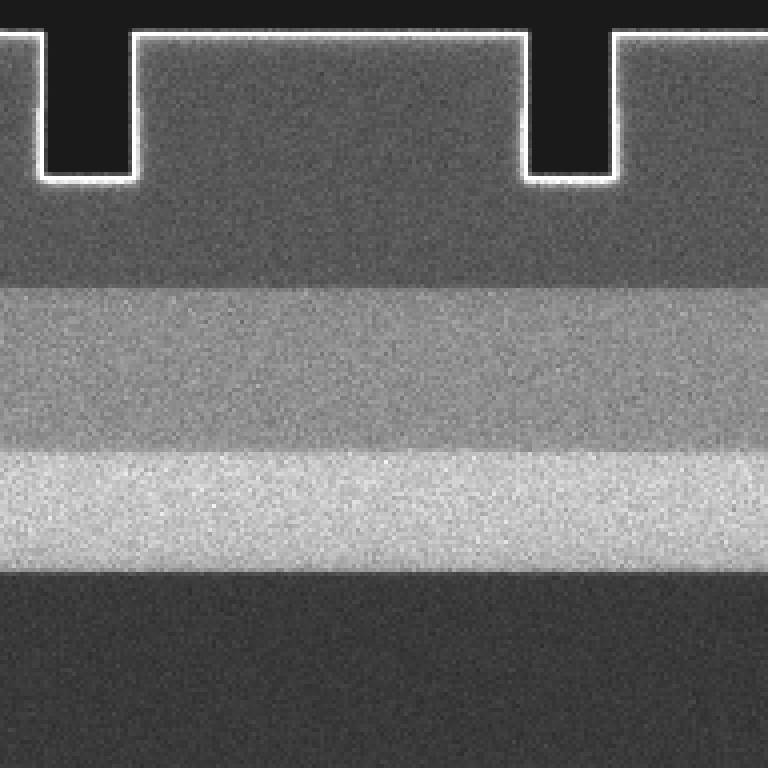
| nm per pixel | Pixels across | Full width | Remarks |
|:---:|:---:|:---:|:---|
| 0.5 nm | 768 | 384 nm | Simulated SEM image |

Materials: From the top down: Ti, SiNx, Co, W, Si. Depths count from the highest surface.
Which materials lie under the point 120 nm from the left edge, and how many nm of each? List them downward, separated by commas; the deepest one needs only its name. Ti 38, SiNx 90, Co 82, W 60, Si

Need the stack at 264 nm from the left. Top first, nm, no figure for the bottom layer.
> empty 72, SiNx 56, Co 82, W 60, Si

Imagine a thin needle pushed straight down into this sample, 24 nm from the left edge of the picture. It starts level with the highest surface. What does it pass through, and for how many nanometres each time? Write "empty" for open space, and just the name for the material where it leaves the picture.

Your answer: empty 72, SiNx 56, Co 82, W 60, Si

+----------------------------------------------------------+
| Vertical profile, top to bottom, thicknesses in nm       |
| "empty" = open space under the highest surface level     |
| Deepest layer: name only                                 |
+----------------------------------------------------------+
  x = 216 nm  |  Ti 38, SiNx 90, Co 82, W 60, Si